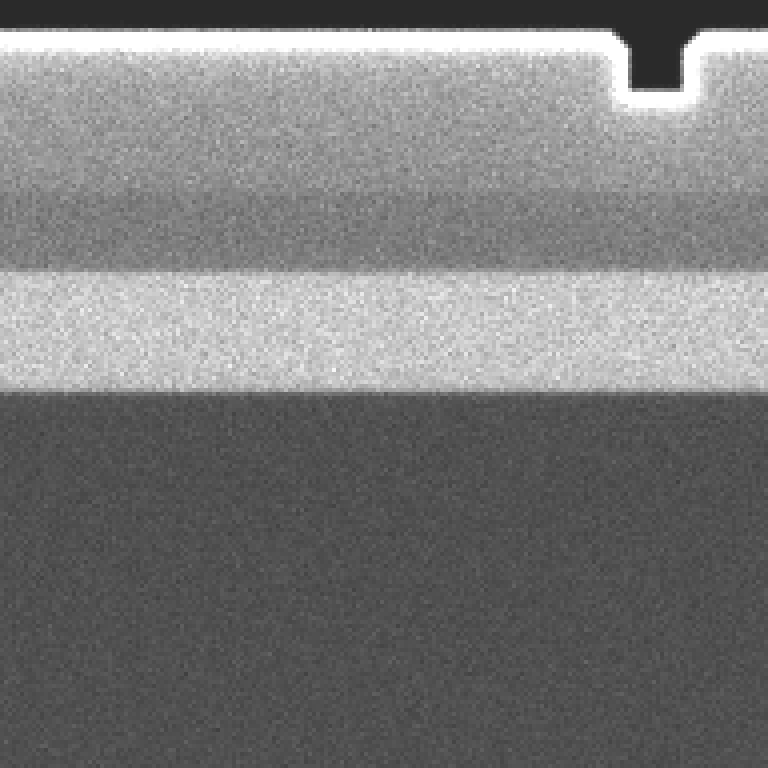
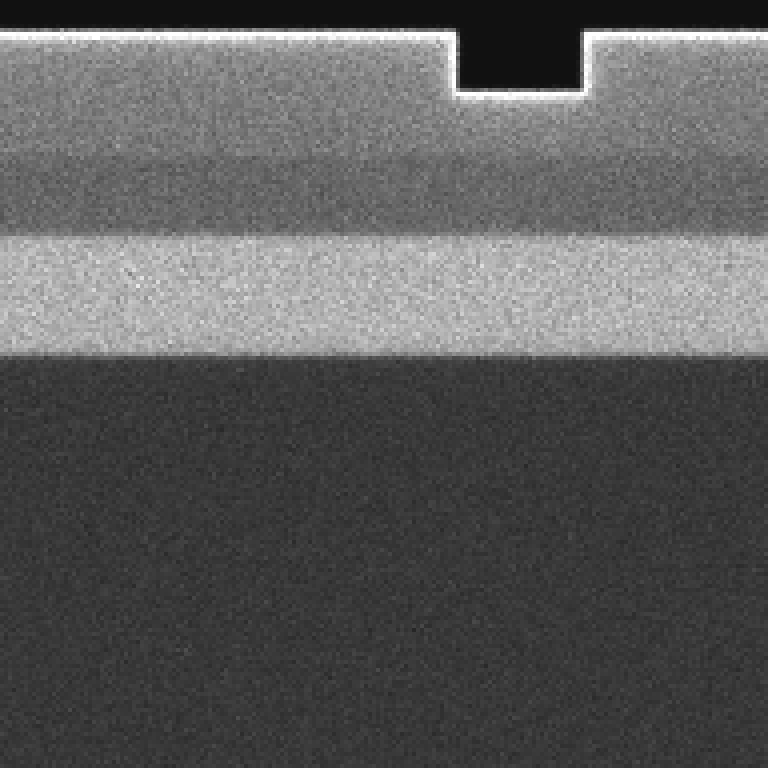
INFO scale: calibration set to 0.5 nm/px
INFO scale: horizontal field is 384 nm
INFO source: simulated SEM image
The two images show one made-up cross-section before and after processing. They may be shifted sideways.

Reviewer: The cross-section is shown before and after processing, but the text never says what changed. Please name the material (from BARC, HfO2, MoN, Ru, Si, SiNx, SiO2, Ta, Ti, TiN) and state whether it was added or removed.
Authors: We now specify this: SiO2, removed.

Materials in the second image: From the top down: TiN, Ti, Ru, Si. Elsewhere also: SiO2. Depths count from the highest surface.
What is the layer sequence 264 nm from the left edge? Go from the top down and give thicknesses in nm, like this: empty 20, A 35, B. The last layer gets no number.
empty 30, TiN 32, Ti 40, Ru 60, Si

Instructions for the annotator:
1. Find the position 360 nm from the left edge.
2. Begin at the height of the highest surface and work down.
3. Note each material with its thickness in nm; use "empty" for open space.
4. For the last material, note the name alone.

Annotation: TiN 62, Ti 40, Ru 60, Si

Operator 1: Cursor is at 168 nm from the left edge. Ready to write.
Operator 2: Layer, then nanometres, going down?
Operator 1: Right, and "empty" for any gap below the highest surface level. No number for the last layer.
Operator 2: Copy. TiN 62, Ti 40, Ru 60, Si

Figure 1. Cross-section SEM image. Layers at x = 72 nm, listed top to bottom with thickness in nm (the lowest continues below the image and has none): TiN 62, Ti 40, Ru 60, Si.